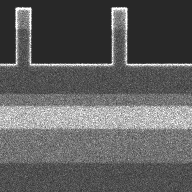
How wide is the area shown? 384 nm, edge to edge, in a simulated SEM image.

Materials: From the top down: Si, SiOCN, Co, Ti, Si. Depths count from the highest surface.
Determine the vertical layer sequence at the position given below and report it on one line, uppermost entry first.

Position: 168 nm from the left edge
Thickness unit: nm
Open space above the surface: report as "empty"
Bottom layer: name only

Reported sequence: empty 112, Si 60, SiOCN 24, Co 46, Ti 68, Si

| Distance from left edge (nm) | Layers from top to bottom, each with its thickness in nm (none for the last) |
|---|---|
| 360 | empty 112, Si 60, SiOCN 24, Co 46, Ti 68, Si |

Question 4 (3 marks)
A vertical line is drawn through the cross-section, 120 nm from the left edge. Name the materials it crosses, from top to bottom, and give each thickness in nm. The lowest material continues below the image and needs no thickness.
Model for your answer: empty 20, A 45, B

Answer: empty 112, Si 60, SiOCN 24, Co 46, Ti 68, Si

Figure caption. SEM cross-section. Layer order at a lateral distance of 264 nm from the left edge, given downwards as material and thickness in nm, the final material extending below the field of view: empty 112, Si 60, SiOCN 24, Co 46, Ti 68, Si